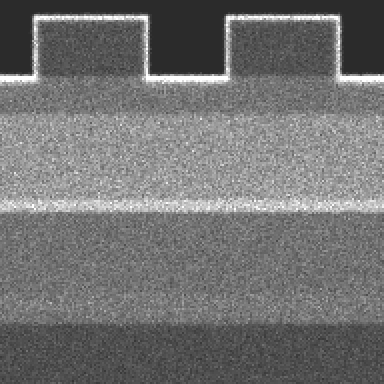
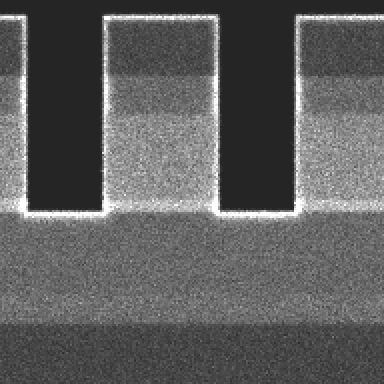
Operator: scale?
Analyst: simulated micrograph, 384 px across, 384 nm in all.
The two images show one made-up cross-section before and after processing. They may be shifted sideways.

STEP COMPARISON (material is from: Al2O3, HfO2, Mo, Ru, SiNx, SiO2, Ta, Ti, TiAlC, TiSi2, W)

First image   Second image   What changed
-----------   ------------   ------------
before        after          Al2O3 and HfO2 and W, removed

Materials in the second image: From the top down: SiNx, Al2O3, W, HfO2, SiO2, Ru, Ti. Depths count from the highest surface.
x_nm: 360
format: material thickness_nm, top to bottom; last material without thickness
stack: SiNx 60, Al2O3 38, W 86, HfO2 12, SiO2 82, Ru 30, Ti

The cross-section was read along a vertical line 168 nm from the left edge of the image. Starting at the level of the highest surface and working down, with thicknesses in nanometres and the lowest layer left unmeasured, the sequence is SiNx 60, Al2O3 38, W 86, HfO2 12, SiO2 82, Ru 30, Ti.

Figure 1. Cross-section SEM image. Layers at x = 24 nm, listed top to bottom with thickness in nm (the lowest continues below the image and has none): SiNx 60, Al2O3 38, W 86, HfO2 12, SiO2 82, Ru 30, Ti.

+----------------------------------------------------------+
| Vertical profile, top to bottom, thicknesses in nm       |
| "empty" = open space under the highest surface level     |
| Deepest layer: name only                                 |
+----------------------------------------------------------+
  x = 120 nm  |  SiNx 60, Al2O3 38, W 86, HfO2 12, SiO2 82, Ru 30, Ti